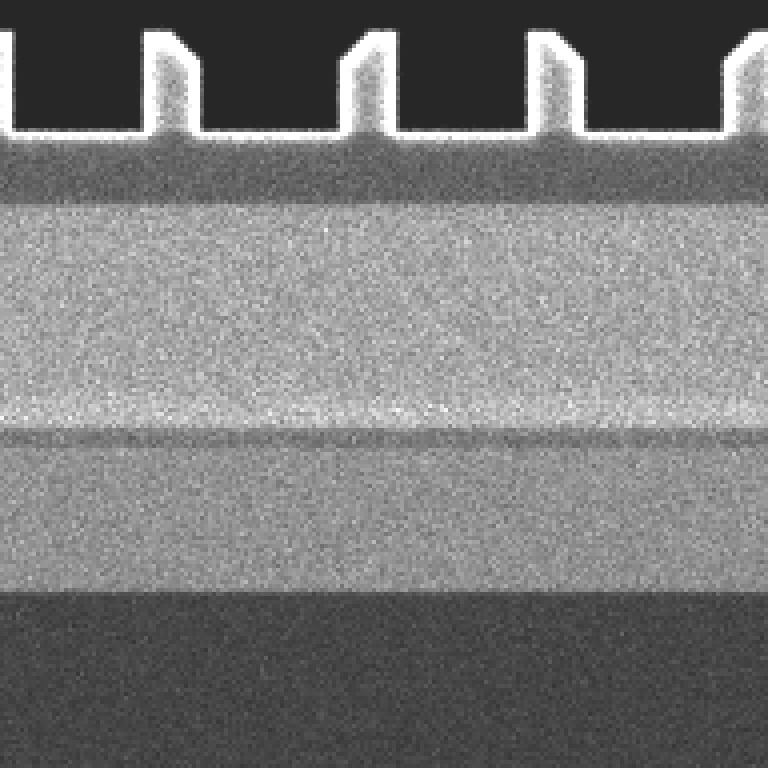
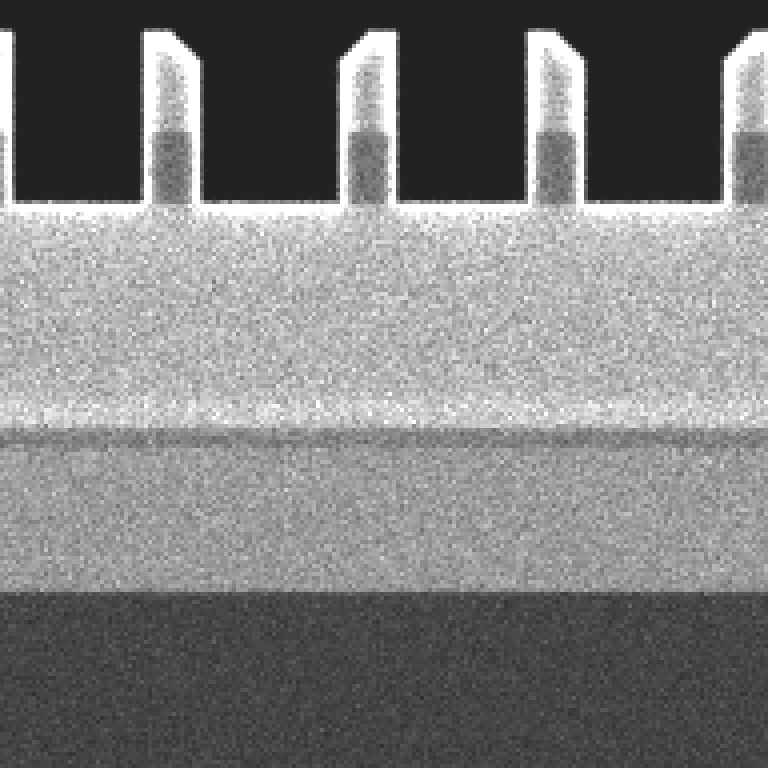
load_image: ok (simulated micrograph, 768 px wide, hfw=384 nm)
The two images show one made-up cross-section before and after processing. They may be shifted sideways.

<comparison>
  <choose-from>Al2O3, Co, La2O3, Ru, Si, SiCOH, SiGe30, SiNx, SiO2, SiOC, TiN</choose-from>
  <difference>SiNx removed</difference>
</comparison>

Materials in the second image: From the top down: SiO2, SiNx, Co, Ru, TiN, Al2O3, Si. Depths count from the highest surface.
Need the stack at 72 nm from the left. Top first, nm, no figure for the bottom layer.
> SiO2 50, SiNx 36, Co 98, Ru 14, TiN 10, Al2O3 72, Si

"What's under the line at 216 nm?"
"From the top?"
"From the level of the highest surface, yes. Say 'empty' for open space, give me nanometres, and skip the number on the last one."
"empty 86, Co 98, Ru 14, TiN 10, Al2O3 72, Si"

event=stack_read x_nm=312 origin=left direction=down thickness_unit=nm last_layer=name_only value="empty 86, Co 98, Ru 14, TiN 10, Al2O3 72, Si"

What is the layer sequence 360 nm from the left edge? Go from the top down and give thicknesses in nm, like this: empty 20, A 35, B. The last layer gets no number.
empty 86, Co 98, Ru 14, TiN 10, Al2O3 72, Si